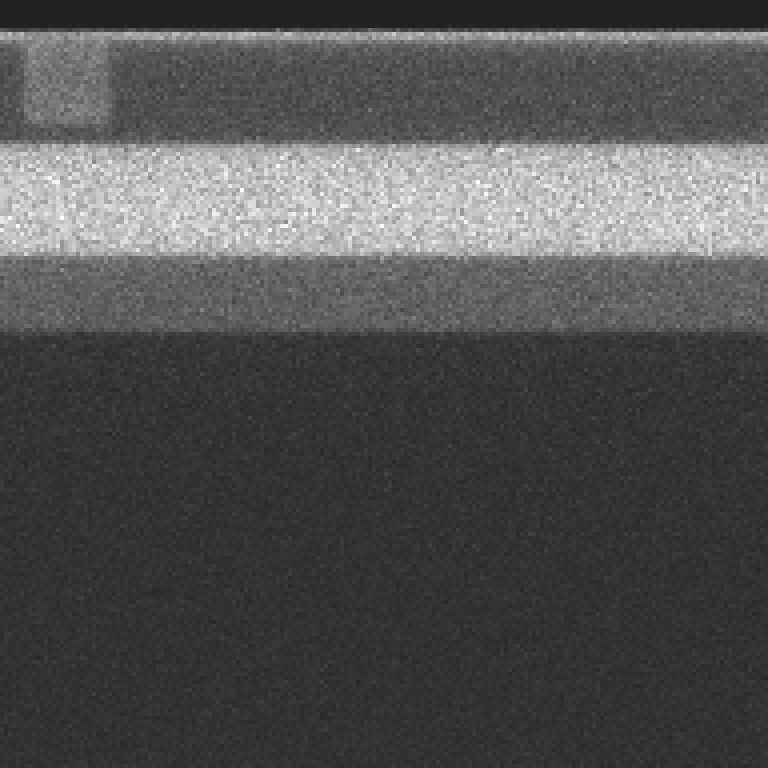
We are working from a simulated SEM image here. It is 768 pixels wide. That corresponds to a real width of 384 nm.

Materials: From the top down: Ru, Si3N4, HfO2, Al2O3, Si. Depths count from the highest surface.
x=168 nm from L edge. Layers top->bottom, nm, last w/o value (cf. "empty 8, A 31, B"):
Si3N4 56, HfO2 56, Al2O3 38, Si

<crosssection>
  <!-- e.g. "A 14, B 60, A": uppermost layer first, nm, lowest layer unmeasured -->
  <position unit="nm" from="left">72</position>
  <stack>Si3N4 56, HfO2 56, Al2O3 38, Si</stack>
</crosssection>